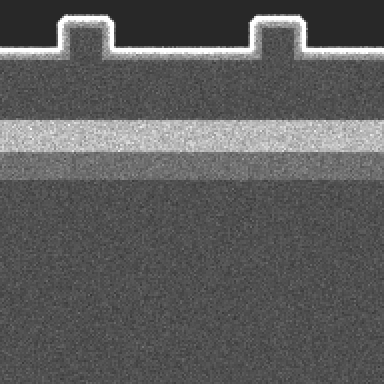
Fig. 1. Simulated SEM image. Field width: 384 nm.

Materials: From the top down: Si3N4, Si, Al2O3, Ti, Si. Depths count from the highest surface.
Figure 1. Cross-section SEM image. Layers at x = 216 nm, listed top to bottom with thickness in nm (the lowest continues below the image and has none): empty 32, Si3N4 12, Si 60, Al2O3 32, Ti 28, Si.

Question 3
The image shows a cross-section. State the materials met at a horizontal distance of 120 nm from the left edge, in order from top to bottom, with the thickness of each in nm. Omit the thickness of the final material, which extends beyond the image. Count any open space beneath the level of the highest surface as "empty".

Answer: empty 32, Si3N4 12, Si 60, Al2O3 32, Ti 28, Si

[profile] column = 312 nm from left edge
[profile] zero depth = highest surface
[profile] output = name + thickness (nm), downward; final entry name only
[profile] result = empty 32, Si3N4 12, Si 60, Al2O3 32, Ti 28, Si